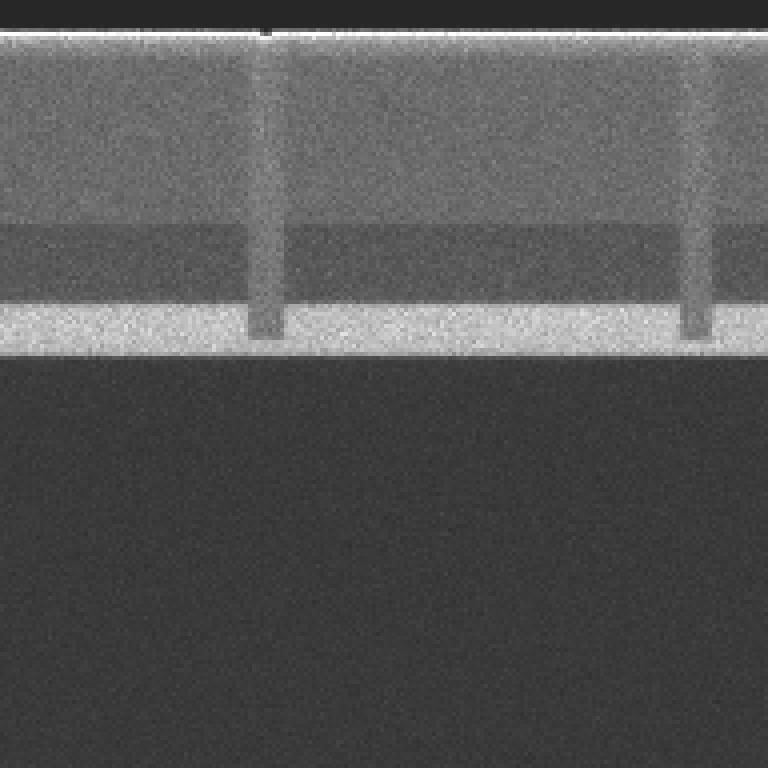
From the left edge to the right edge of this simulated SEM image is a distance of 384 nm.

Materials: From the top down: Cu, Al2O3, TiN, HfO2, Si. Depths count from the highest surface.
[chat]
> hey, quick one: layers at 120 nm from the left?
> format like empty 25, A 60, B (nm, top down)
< Cu 12, Al2O3 84, TiN 40, HfO2 26, Si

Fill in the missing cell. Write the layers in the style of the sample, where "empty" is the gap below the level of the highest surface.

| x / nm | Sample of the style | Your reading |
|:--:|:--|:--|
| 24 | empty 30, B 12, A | Cu 12, Al2O3 84, TiN 40, HfO2 26, Si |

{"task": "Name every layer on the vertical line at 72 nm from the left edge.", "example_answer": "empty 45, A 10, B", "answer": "Cu 12, Al2O3 84, TiN 40, HfO2 26, Si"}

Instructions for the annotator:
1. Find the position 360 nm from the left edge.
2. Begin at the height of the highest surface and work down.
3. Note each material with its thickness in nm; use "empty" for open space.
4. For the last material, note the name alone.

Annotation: Cu 12, Al2O3 84, TiN 40, HfO2 26, Si